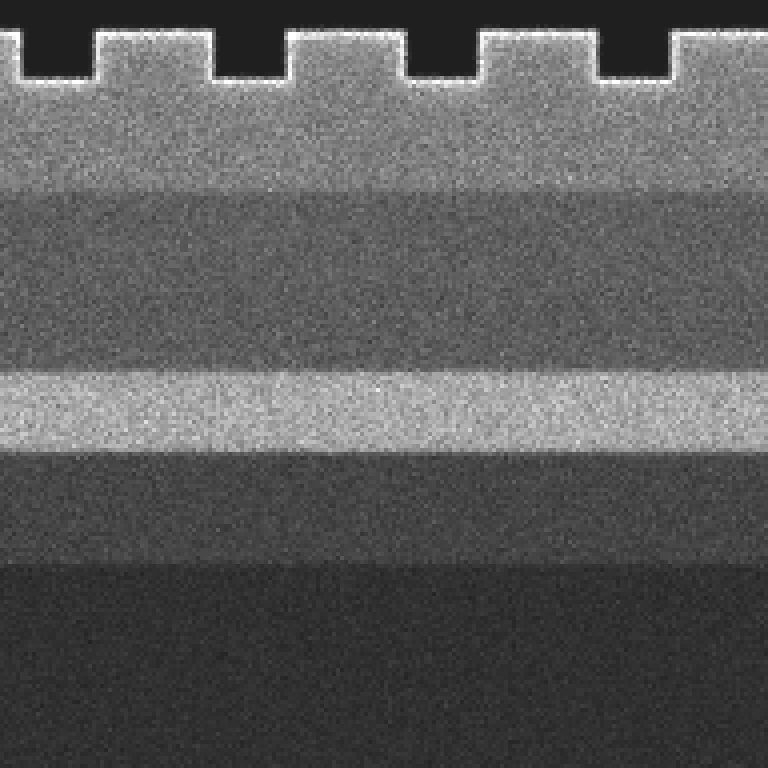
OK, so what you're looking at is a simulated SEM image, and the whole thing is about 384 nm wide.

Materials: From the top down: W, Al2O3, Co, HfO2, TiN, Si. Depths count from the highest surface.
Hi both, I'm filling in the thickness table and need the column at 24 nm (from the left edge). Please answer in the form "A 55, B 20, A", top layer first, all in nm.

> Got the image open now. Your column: empty 24, W 56, Al2O3 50, Co 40, HfO2 40, TiN 56, Si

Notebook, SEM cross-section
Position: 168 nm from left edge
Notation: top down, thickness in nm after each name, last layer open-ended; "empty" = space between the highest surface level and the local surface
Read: W 80, Al2O3 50, Co 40, HfO2 40, TiN 56, Si